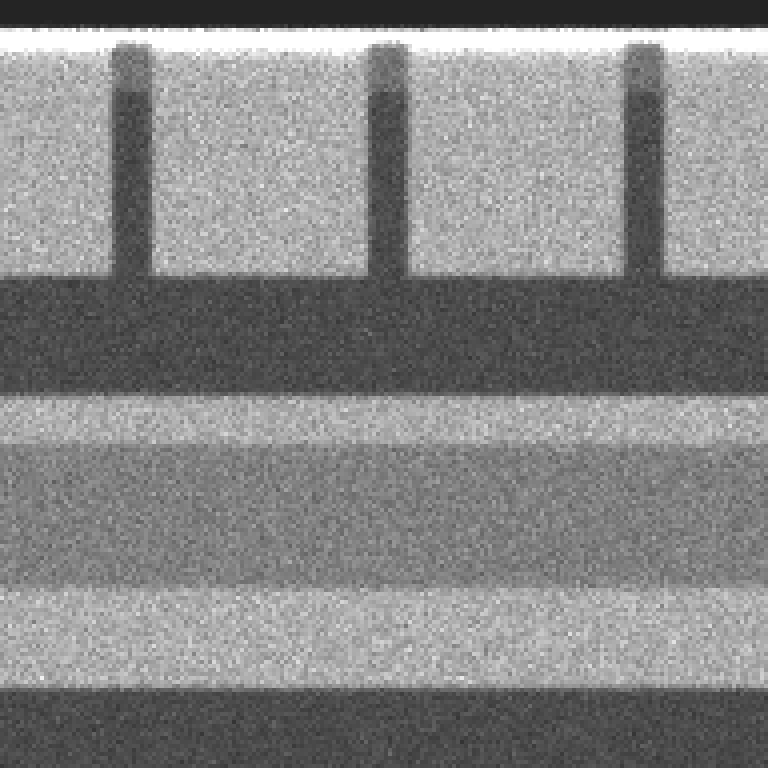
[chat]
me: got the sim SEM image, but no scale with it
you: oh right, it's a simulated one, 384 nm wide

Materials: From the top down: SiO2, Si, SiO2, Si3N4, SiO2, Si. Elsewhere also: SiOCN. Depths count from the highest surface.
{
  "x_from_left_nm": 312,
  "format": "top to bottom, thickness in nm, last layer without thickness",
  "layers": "SiOCN 30, Si 152, SiO2 24, Si3N4 72, SiO2 50, Si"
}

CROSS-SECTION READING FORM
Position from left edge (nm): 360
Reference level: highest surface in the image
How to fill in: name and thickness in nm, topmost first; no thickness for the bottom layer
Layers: SiO2 122, Si 60, SiO2 24, Si3N4 72, SiO2 50, Si